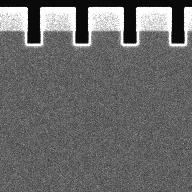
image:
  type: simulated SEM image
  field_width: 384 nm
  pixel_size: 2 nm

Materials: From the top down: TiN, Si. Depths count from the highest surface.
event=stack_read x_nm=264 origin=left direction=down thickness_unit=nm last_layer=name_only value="empty 72, Si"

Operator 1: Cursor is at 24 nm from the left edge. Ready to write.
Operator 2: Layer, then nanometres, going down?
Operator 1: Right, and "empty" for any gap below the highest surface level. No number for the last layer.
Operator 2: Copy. TiN 46, Si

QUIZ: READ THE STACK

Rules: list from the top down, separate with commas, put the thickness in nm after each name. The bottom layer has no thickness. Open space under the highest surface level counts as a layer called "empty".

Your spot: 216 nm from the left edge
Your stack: TiN 46, Si